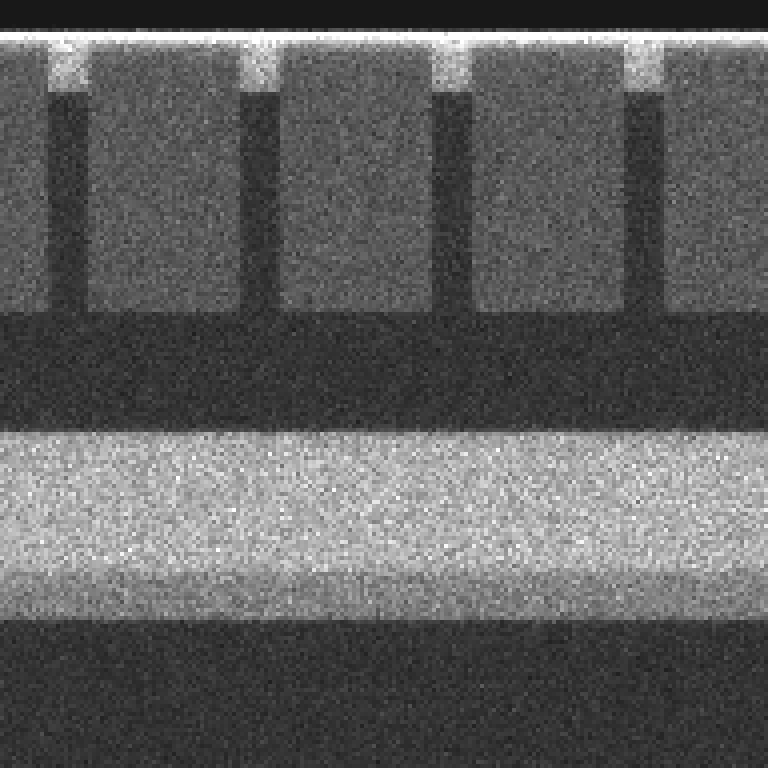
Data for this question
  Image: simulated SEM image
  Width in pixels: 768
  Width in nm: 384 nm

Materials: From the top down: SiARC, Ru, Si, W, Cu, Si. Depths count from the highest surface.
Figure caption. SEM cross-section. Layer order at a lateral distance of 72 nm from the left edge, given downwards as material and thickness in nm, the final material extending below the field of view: SiARC 140, Si 60, W 70, Cu 24, Si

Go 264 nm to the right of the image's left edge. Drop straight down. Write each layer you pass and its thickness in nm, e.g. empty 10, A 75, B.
SiARC 140, Si 60, W 70, Cu 24, Si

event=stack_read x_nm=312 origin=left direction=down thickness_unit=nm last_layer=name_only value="SiARC 6, Ru 24, Si 170, W 70, Cu 24, Si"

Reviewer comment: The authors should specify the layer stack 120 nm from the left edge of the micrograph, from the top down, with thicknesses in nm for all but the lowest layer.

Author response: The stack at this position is SiARC 6, Ru 24, Si 170, W 70, Cu 24, Si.